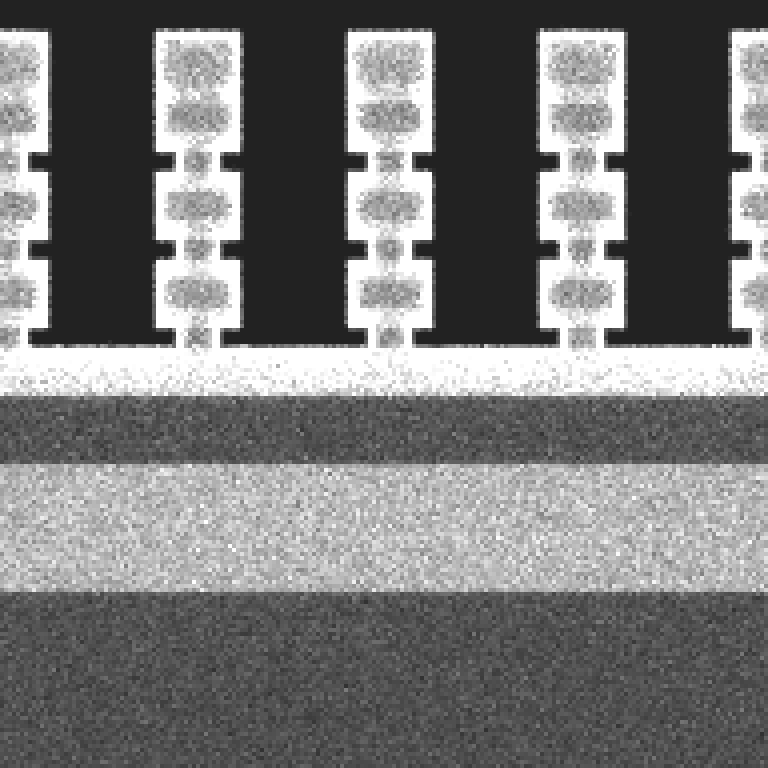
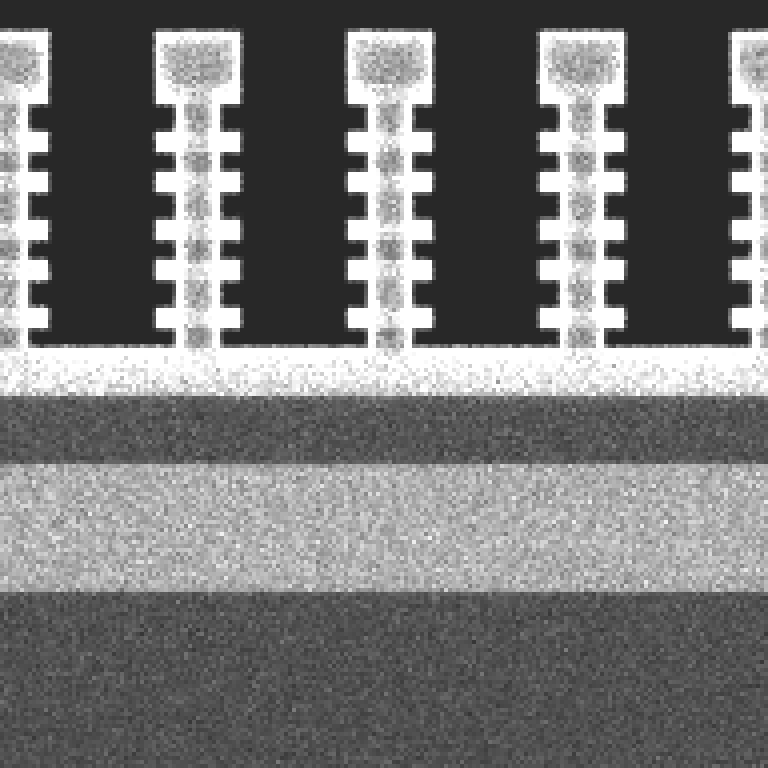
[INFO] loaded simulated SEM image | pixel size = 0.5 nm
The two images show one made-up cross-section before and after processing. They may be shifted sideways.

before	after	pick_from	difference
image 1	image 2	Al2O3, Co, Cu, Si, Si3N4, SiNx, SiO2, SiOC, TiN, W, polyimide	Si3N4 removed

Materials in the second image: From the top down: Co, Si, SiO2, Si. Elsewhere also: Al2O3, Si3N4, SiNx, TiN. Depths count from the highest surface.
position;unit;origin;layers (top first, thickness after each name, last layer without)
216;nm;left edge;empty 158, Co 24, Si 34, SiO2 64, Si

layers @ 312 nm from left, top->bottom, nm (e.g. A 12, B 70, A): empty 158, Co 24, Si 34, SiO2 64, Si